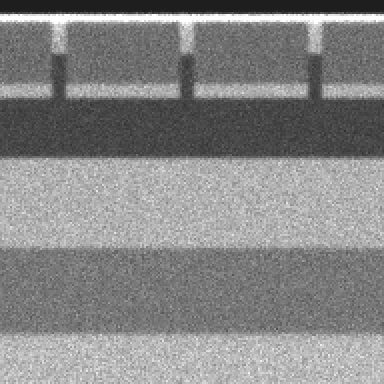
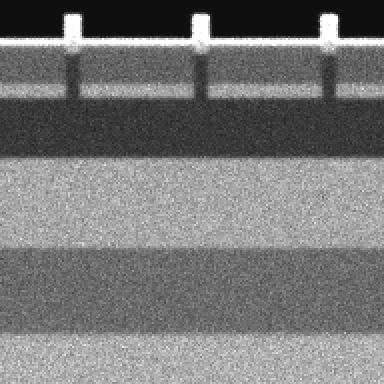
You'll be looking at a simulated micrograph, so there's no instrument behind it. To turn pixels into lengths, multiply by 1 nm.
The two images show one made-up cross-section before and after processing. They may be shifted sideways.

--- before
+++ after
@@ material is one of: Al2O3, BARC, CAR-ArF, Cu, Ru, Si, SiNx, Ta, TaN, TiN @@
SiNx removed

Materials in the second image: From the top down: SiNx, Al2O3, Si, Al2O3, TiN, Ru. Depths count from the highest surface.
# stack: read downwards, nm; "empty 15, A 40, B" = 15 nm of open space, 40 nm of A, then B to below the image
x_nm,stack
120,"empty 24, SiNx 44, Al2O3 14, Si 60, Al2O3 90, TiN 86, Ru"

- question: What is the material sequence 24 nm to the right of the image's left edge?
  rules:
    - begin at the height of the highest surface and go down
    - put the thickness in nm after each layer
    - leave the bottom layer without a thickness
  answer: empty 24, SiNx 44, Al2O3 14, Si 60, Al2O3 90, TiN 86, Ru